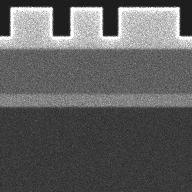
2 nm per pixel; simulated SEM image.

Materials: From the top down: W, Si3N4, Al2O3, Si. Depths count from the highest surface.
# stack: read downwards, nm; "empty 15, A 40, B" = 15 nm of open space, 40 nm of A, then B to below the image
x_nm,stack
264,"W 82, Si3N4 90, Al2O3 26, Si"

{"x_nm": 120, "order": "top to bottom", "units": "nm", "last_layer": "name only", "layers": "empty 58, W 24, Si3N4 90, Al2O3 26, Si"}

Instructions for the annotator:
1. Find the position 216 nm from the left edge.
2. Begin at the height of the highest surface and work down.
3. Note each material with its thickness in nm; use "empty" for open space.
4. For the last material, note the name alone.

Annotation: empty 58, W 24, Si3N4 90, Al2O3 26, Si